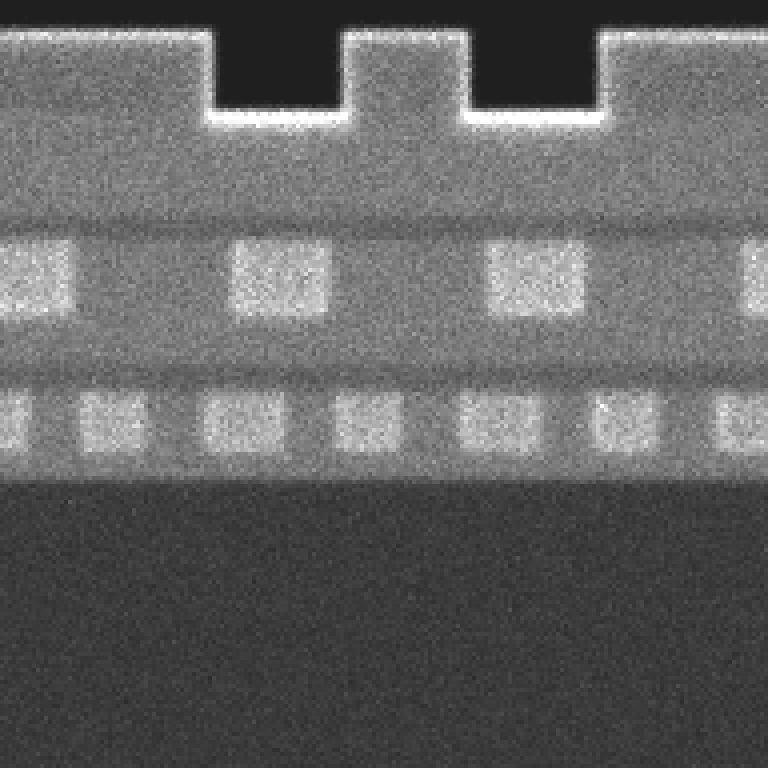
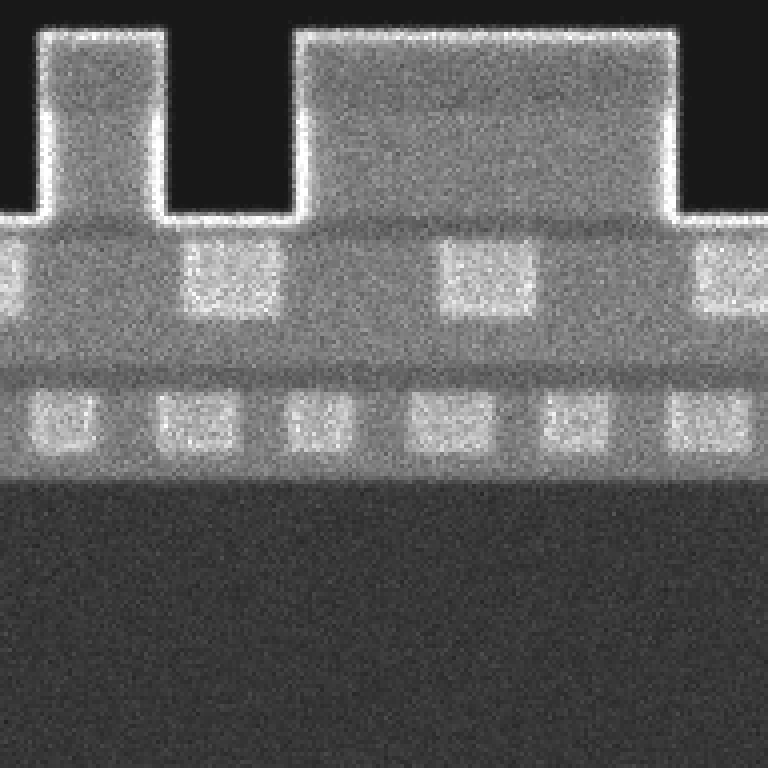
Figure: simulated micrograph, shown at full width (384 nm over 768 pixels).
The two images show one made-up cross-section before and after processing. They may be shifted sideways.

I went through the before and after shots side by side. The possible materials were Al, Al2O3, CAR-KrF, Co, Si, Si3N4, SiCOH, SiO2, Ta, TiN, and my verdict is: removed, SiO2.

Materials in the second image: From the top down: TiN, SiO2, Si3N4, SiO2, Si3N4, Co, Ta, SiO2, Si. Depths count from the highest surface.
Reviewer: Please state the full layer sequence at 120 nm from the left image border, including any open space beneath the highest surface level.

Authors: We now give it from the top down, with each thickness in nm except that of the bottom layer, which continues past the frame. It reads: empty 92, Si3N4 12, Co 32, Ta 6, SiO2 24, Si3N4 14, SiO2 44, Si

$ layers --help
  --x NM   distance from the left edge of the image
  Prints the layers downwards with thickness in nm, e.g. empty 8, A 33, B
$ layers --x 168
TiN 40, SiO2 52, Si3N4 12, SiO2 62, Si3N4 14, Co 24, Ta 6, SiO2 14, Si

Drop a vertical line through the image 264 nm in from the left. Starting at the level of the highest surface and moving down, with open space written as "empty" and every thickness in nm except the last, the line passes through TiN 40, SiO2 52, Si3N4 12, Ta 38, SiO2 24, Si3N4 14, SiO2 44, Si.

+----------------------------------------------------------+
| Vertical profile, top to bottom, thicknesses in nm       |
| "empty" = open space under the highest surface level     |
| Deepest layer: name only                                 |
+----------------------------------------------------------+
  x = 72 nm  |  TiN 40, SiO2 52, Si3N4 12, SiO2 62, Si3N4 14, SiO2 44, Si